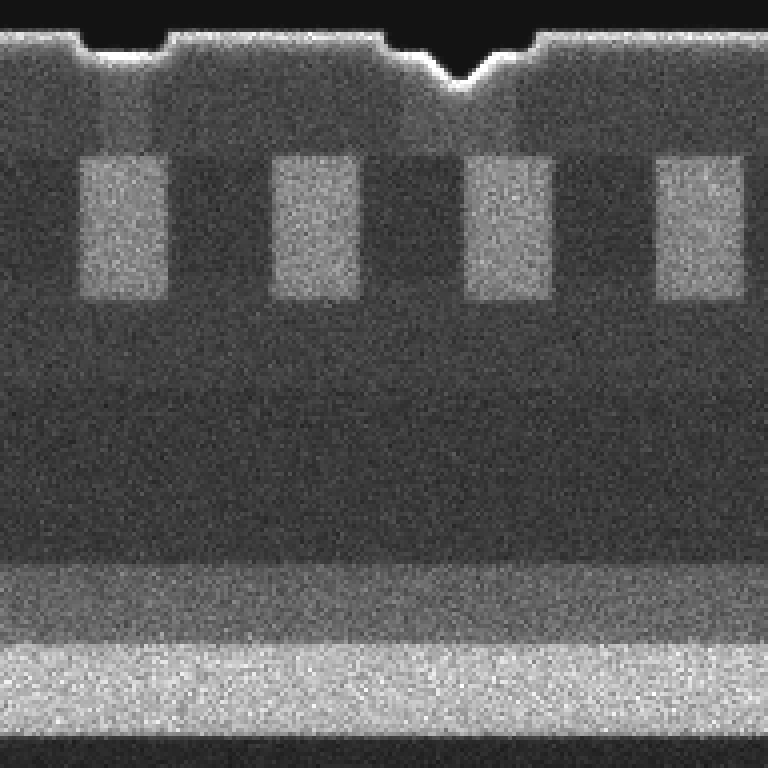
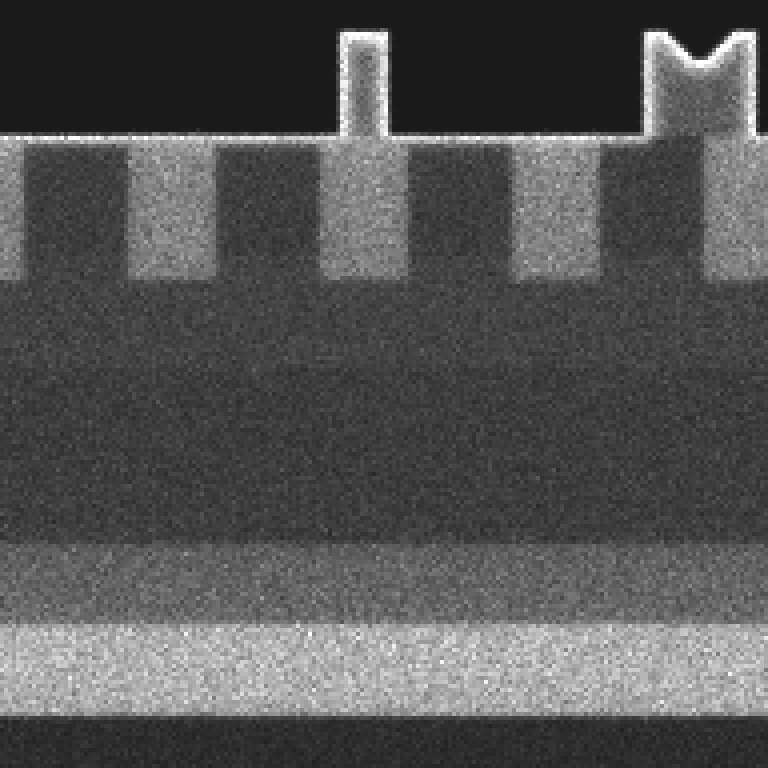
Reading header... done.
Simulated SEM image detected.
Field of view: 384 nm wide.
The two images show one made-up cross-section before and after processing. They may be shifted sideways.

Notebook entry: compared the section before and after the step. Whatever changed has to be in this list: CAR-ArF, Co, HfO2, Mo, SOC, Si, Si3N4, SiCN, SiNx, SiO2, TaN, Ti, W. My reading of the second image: SOC removed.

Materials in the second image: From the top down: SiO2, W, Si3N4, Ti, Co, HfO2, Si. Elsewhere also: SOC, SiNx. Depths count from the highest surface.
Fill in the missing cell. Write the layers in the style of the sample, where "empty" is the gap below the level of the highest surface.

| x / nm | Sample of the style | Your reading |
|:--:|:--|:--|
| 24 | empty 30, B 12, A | empty 52, SiNx 60, Si3N4 56, Ti 88, Co 40, HfO2 46, Si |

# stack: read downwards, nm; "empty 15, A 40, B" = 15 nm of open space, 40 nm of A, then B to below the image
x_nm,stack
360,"empty 6, SiO2 46, W 72, Si3N4 44, Ti 88, Co 40, HfO2 46, Si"